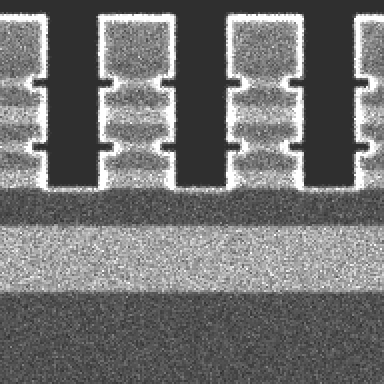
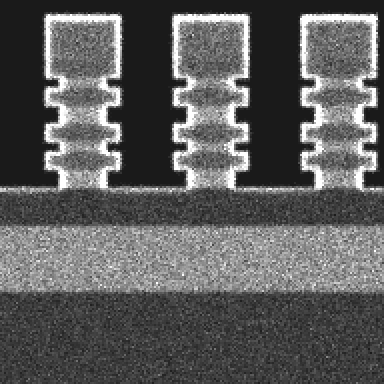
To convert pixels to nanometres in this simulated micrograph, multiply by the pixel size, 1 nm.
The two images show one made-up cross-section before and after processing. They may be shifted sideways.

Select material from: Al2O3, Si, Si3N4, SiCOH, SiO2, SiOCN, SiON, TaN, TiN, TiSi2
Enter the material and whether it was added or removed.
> Al2O3 / removed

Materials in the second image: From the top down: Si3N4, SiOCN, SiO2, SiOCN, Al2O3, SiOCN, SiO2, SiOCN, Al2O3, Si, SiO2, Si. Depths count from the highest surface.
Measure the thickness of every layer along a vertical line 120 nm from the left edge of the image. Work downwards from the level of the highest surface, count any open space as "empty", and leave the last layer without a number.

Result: empty 172, Si 38, SiO2 66, Si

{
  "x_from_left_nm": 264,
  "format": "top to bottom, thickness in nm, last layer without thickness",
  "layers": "empty 172, Si 38, SiO2 66, Si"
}